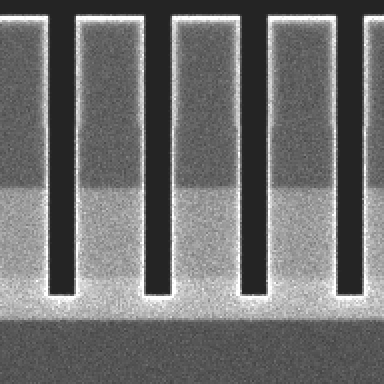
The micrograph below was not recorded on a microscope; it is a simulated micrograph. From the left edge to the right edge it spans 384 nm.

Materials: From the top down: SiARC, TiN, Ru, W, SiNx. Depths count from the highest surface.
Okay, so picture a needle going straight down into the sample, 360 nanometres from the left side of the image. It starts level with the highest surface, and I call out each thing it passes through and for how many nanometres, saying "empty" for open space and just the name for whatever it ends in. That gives empty 280, W 24, SiNx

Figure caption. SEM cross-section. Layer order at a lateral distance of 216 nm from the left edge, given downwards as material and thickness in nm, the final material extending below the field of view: SiARC 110, TiN 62, Ru 90, W 42, SiNx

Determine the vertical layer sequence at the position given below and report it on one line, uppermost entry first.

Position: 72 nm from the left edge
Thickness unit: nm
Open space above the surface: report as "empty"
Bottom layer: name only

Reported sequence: empty 280, W 24, SiNx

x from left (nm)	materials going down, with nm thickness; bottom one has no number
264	empty 280, W 24, SiNx